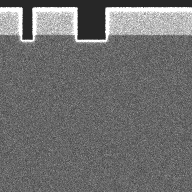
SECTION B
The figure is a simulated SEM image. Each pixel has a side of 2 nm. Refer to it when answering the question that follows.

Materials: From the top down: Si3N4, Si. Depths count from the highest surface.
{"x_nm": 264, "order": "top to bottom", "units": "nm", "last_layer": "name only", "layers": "Si3N4 54, Si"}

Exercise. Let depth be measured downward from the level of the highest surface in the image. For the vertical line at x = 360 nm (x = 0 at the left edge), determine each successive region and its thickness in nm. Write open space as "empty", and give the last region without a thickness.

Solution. Si3N4 54, Si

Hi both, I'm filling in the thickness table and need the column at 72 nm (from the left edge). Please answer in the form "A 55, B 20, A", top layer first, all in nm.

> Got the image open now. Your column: Si3N4 54, Si